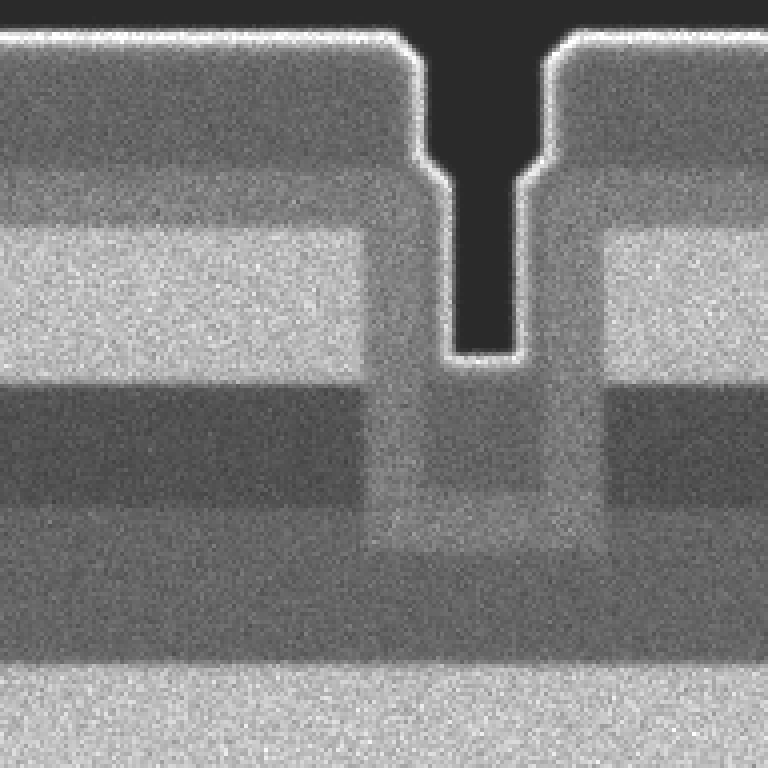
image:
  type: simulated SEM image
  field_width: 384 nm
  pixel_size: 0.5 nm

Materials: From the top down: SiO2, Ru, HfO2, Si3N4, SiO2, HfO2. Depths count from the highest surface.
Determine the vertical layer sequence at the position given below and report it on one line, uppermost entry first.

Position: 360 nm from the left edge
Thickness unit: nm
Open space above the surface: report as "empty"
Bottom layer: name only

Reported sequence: SiO2 68, Ru 30, HfO2 78, Si3N4 62, SiO2 78, HfO2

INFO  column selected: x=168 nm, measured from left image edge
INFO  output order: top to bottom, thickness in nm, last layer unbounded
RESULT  SiO2 68, Ru 30, HfO2 78, Si3N4 62, SiO2 78, HfO2